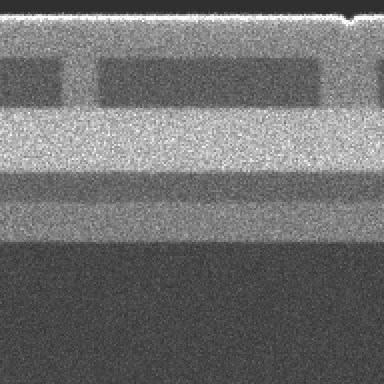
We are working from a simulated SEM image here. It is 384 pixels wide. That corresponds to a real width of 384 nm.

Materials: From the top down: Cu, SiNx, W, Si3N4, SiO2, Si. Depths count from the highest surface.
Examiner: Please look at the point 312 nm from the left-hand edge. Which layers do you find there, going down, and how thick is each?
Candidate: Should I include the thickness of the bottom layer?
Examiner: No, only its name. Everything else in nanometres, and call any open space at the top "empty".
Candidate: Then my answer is Cu 42, SiNx 50, W 64, Si3N4 30, SiO2 40, Si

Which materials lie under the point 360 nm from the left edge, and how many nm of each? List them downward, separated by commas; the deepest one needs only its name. Cu 92, W 64, Si3N4 30, SiO2 40, Si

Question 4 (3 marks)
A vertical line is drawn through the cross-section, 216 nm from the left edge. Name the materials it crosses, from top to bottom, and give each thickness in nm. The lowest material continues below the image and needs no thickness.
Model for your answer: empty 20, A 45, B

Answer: Cu 42, SiNx 50, W 64, Si3N4 30, SiO2 40, Si